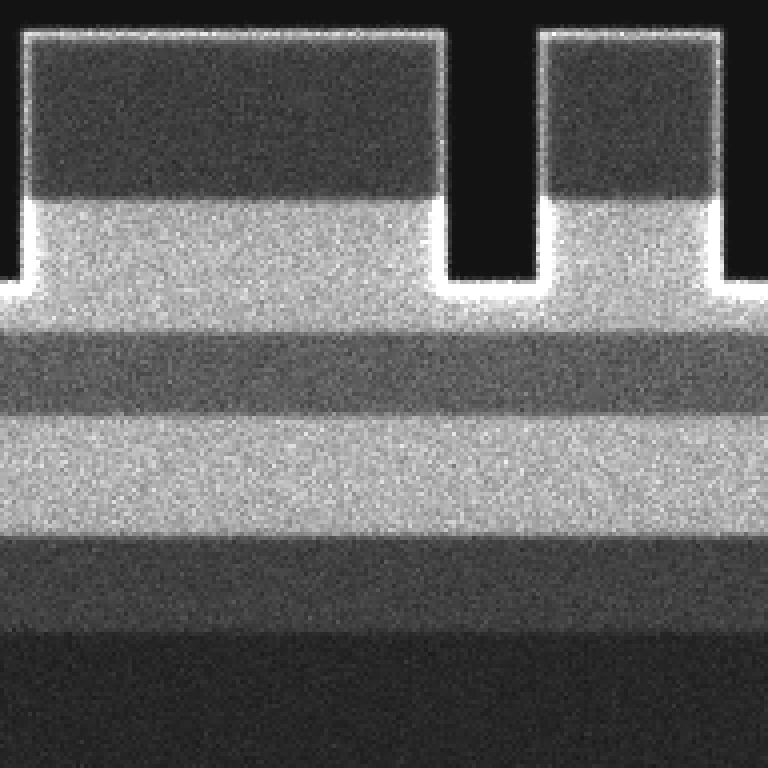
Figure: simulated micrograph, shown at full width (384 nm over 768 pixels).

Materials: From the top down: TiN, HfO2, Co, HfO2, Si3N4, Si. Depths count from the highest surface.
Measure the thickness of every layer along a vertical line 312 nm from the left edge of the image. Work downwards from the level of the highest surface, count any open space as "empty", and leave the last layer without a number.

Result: TiN 84, HfO2 66, Co 42, HfO2 60, Si3N4 48, Si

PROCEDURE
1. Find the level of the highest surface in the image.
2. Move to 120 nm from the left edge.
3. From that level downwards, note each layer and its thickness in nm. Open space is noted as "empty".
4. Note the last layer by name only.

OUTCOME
TiN 84, HfO2 66, Co 42, HfO2 60, Si3N4 48, Si